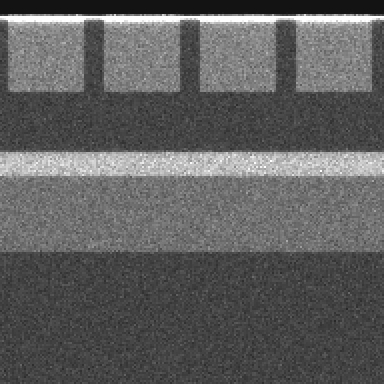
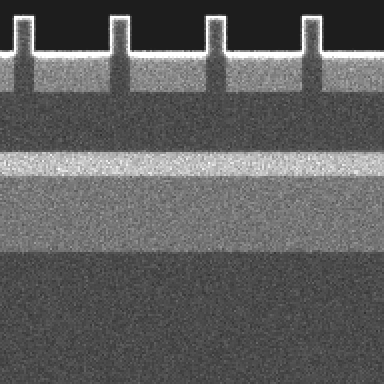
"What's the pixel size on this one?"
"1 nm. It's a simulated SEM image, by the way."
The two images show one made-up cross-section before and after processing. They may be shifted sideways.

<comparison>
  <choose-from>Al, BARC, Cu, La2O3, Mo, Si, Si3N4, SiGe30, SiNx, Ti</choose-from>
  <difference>Si3N4 removed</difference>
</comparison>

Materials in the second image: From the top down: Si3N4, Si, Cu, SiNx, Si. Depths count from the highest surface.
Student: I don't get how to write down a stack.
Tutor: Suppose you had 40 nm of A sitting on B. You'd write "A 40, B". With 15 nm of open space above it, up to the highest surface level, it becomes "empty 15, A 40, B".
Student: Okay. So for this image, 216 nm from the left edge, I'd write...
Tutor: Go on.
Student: Si 136, Cu 24, SiNx 76, Si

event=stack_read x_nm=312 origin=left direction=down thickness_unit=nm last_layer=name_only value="Si 136, Cu 24, SiNx 76, Si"